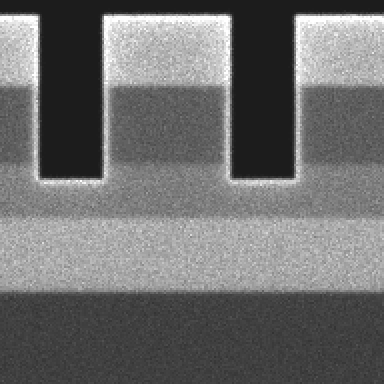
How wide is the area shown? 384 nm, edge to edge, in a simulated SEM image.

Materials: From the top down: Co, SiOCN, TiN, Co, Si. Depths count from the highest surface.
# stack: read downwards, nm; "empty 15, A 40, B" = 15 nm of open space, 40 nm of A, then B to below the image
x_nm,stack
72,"empty 164, TiN 38, Co 74, Si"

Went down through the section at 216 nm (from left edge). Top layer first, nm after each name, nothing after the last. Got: Co 70, SiOCN 78, TiN 54, Co 74, Si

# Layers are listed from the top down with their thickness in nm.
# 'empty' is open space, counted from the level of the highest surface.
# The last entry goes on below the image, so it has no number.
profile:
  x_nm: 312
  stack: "Co 70, SiOCN 78, TiN 54, Co 74, Si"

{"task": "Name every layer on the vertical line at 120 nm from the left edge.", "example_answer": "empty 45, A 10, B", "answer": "Co 70, SiOCN 78, TiN 54, Co 74, Si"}